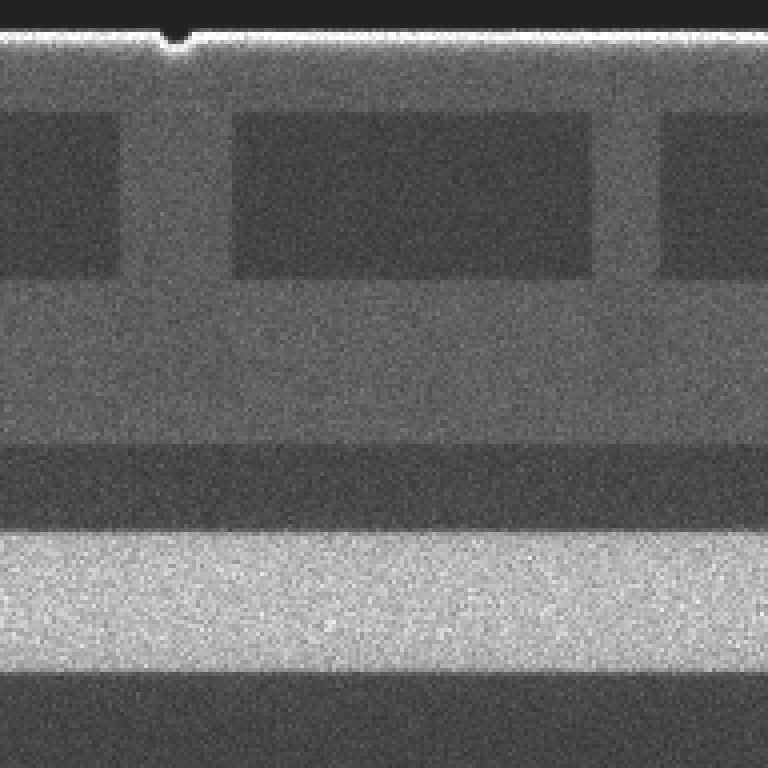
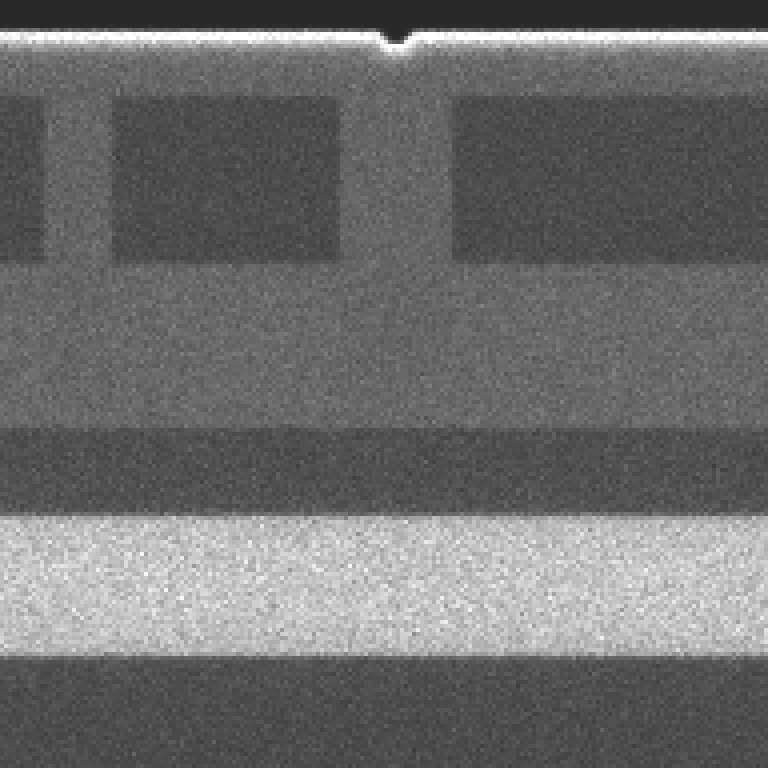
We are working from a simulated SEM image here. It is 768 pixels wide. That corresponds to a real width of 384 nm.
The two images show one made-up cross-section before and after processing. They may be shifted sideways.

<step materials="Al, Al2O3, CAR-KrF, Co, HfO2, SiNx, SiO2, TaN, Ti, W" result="removed SiO2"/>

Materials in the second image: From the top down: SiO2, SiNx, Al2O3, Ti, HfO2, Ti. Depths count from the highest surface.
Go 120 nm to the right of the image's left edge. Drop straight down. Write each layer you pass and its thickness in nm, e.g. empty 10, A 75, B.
SiO2 32, SiNx 84, Al2O3 82, Ti 44, HfO2 70, Ti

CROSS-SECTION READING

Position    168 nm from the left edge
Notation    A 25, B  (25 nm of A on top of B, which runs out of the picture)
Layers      SiO2 32, SiNx 84, Al2O3 82, Ti 44, HfO2 70, Ti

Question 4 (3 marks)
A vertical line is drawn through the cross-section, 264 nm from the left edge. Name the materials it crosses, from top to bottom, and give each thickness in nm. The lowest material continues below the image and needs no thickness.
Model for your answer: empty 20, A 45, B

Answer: SiO2 32, SiNx 84, Al2O3 82, Ti 44, HfO2 70, Ti